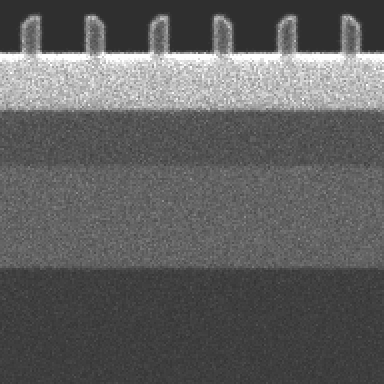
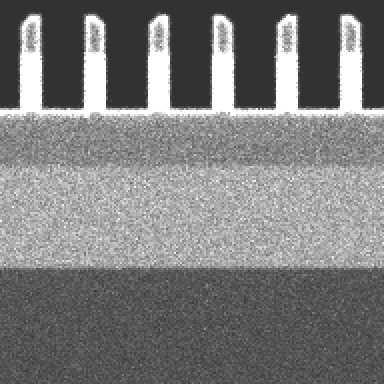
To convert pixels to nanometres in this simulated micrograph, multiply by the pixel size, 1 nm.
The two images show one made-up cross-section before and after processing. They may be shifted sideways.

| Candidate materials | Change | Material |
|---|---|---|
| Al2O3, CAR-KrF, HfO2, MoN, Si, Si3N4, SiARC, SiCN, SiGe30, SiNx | removed | HfO2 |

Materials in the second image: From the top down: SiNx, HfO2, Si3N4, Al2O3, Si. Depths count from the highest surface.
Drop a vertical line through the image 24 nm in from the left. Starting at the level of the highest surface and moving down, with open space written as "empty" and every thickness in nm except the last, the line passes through empty 6, SiNx 32, HfO2 56, Si3N4 56, Al2O3 102, Si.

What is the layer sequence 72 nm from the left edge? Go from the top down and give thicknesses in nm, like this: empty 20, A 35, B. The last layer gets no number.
empty 94, Si3N4 56, Al2O3 102, Si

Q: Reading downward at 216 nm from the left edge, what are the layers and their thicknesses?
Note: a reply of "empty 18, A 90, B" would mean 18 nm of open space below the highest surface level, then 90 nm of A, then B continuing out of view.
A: SiNx 38, HfO2 56, Si3N4 56, Al2O3 102, Si